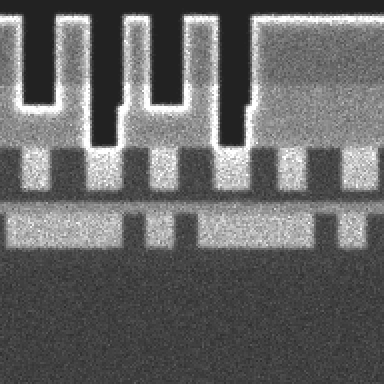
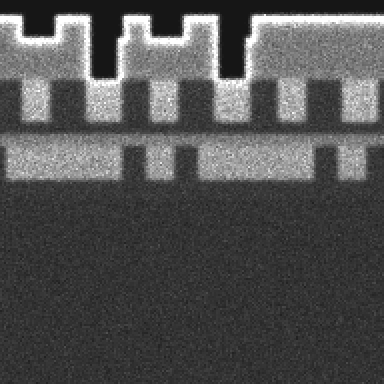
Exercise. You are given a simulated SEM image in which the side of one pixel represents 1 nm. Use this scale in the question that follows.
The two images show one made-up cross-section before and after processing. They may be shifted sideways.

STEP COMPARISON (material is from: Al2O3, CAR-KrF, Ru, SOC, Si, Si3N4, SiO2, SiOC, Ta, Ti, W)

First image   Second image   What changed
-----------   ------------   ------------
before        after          SOC, removed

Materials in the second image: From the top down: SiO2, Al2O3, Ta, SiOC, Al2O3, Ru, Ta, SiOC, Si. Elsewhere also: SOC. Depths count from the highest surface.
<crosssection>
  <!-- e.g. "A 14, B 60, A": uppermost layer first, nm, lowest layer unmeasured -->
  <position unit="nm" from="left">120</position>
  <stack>empty 22, SiO2 32, Al2O3 10, Ta 42, SiOC 12, Al2O3 12, Ta 34, SiOC 20, Si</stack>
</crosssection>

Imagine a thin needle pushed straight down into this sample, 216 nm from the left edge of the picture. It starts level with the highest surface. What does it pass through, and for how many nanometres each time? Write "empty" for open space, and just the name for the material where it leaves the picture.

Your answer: SiO2 54, Al2O3 10, Ta 42, SiOC 12, Al2O3 12, Ru 26, Ta 8, SiOC 20, Si